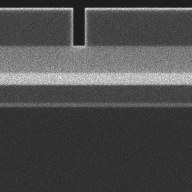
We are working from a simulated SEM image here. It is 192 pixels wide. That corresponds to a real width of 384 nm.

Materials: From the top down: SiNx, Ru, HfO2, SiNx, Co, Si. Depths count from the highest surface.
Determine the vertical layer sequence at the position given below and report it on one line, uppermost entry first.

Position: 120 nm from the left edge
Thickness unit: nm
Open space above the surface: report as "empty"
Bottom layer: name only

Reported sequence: SiNx 76, Ru 54, HfO2 24, SiNx 36, Co 8, Si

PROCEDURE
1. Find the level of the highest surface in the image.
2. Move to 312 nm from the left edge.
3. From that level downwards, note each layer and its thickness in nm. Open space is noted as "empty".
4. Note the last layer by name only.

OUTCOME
SiNx 76, Ru 54, HfO2 24, SiNx 36, Co 8, Si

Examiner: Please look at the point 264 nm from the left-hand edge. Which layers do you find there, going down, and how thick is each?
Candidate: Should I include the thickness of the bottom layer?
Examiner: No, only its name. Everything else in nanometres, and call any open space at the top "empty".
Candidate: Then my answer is SiNx 76, Ru 54, HfO2 24, SiNx 36, Co 8, Si